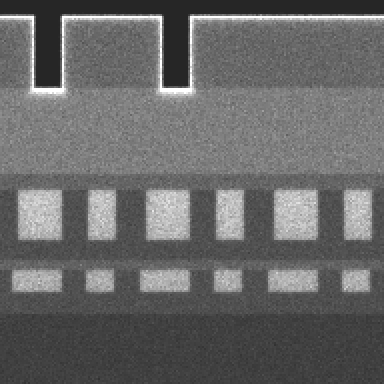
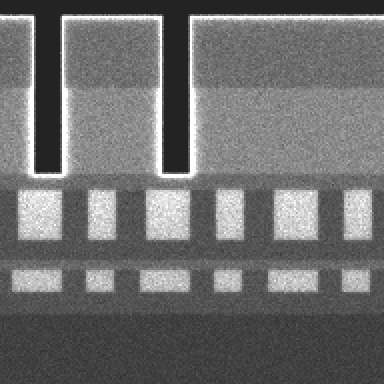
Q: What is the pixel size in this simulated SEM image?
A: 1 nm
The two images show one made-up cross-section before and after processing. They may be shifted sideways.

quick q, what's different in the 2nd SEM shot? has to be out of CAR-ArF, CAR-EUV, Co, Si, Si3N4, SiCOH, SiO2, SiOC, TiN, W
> SiO2 removed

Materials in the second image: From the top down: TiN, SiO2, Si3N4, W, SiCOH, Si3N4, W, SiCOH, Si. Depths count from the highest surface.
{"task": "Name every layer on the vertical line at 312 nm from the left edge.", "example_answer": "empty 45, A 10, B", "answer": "TiN 72, SiO2 86, Si3N4 16, W 50, SiCOH 20, Si3N4 10, W 22, SiCOH 22, Si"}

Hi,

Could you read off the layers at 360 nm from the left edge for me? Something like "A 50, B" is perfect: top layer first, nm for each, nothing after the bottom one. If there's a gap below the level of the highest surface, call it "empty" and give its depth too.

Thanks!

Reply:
TiN 72, SiO2 86, Si3N4 16, W 50, SiCOH 20, Si3N4 10, W 22, SiCOH 22, Si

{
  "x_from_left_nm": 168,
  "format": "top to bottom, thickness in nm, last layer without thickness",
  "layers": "empty 158, Si3N4 16, W 50, SiCOH 20, Si3N4 10, W 22, SiCOH 22, Si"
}